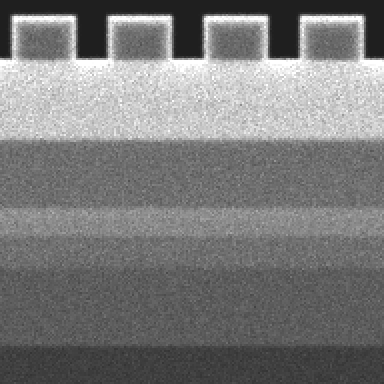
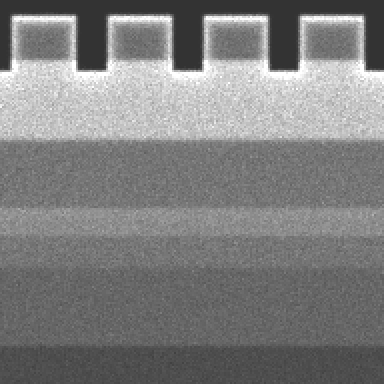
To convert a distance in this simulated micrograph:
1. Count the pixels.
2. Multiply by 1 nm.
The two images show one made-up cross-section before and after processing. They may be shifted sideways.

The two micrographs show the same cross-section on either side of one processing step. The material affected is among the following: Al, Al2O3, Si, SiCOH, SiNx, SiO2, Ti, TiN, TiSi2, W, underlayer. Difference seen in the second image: W removed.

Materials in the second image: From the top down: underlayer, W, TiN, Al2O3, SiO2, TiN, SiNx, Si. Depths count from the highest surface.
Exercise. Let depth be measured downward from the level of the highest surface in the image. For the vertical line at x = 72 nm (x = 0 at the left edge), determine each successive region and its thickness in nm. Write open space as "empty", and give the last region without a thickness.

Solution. underlayer 44, W 80, TiN 68, Al2O3 12, SiO2 16, TiN 32, SiNx 78, Si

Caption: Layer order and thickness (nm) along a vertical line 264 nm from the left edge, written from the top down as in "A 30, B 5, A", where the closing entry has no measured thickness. underlayer 44, W 80, TiN 68, Al2O3 12, SiO2 16, TiN 32, SiNx 78, Si